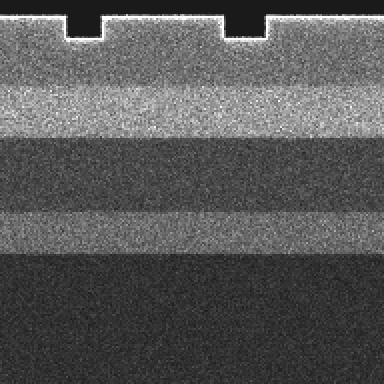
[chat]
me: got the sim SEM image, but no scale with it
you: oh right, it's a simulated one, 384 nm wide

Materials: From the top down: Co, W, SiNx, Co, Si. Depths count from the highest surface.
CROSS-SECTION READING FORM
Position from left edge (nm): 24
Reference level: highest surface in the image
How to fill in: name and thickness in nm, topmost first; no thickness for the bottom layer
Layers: Co 70, W 52, SiNx 74, Co 42, Si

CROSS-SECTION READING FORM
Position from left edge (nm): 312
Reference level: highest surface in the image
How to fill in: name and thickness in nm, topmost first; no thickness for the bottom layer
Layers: Co 70, W 52, SiNx 74, Co 42, Si